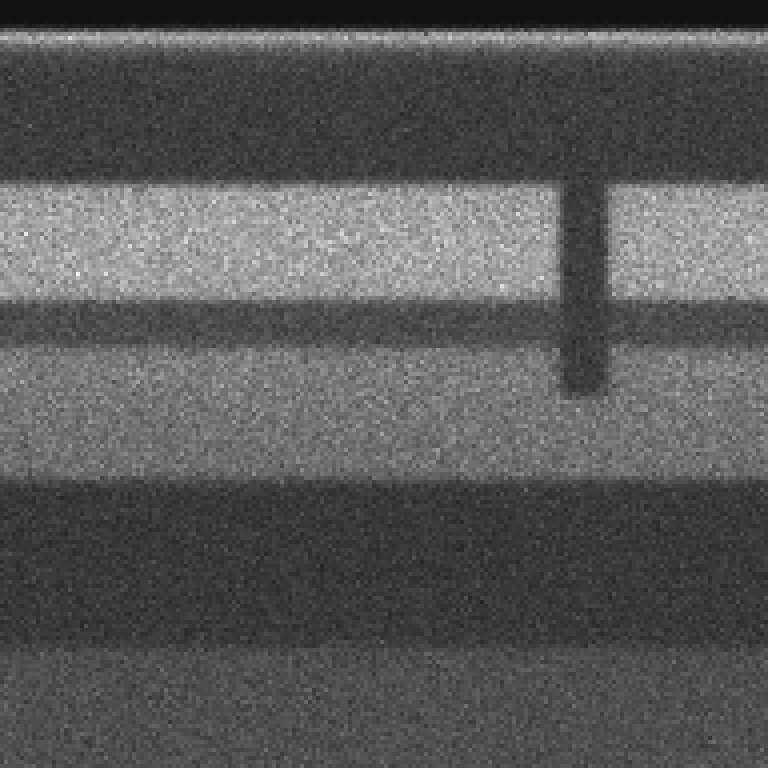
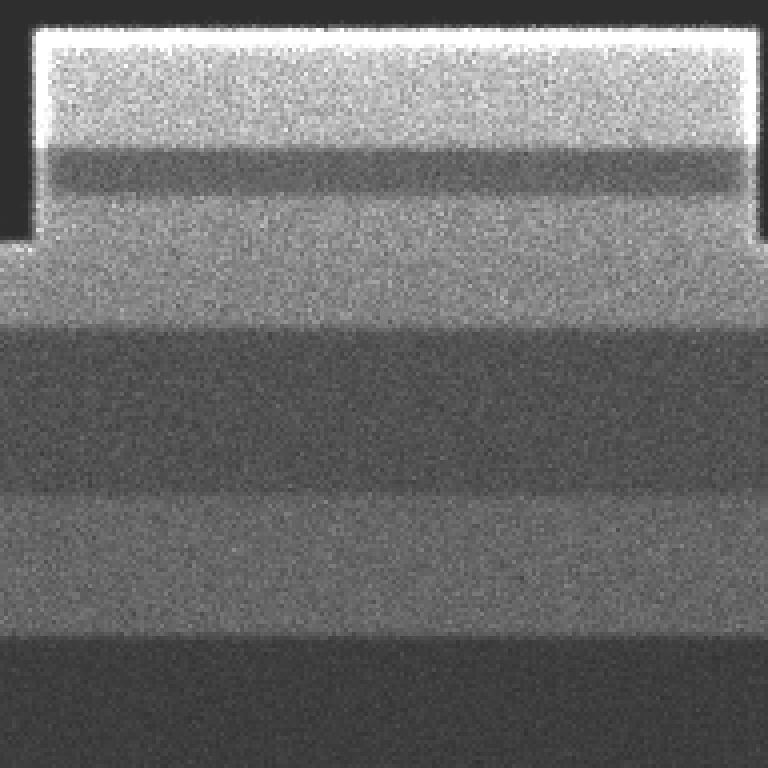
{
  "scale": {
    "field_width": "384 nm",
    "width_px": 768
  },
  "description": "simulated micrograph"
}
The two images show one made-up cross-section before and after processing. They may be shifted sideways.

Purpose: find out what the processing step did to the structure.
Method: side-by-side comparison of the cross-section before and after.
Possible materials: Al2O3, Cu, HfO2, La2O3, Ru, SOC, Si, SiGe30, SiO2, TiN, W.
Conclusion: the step removed SOC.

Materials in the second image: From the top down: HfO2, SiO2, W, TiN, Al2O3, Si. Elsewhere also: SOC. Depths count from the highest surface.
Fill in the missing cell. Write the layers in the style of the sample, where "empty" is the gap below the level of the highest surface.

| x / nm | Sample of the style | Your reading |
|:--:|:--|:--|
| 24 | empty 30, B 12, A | HfO2 58, SiO2 24, W 66, TiN 84, Al2O3 70, Si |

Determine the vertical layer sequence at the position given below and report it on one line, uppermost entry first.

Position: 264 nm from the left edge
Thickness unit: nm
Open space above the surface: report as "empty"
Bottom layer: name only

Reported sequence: HfO2 58, SiO2 24, W 66, TiN 84, Al2O3 70, Si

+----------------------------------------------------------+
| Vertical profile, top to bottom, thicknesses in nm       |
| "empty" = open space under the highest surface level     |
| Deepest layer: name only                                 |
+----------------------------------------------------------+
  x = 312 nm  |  HfO2 58, SiO2 24, W 66, TiN 84, Al2O3 70, Si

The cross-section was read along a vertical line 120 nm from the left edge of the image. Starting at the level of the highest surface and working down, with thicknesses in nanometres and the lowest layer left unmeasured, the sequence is HfO2 58, SiO2 24, W 66, TiN 84, Al2O3 70, Si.